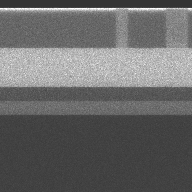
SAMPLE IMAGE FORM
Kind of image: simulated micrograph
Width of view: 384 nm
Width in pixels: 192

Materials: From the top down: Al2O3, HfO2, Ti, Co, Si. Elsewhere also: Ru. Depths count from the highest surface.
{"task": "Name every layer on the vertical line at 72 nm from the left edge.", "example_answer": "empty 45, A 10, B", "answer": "Al2O3 80, HfO2 78, Ti 28, Co 28, Si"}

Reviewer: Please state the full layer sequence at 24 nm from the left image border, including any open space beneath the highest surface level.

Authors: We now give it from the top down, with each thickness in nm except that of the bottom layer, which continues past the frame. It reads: Al2O3 80, HfO2 78, Ti 28, Co 28, Si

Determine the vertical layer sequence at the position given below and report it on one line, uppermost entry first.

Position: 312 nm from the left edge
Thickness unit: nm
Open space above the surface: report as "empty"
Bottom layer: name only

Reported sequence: Al2O3 80, HfO2 78, Ti 28, Co 28, Si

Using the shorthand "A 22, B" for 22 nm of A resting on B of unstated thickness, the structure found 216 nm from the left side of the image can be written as Al2O3 80, HfO2 78, Ti 28, Co 28, Si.